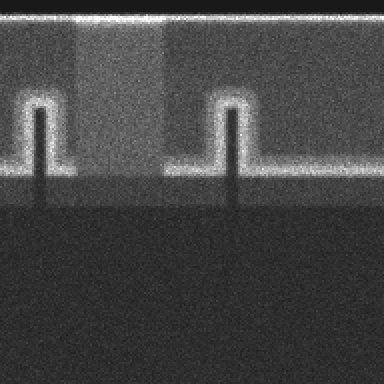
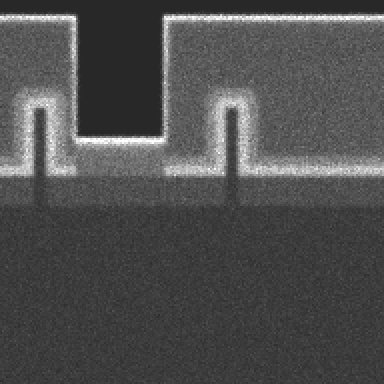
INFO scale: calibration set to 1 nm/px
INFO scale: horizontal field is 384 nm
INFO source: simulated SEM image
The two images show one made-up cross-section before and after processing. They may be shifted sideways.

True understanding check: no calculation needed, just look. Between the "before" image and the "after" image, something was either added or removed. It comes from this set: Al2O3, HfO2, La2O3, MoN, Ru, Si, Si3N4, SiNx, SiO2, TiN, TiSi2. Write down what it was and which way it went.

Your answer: SiO2 (removed)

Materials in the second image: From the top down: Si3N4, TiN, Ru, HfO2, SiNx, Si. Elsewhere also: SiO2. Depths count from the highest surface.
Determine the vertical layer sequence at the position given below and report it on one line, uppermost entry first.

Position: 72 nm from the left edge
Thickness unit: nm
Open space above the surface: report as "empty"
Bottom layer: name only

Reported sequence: Si3N4 44, TiN 96, Ru 10, HfO2 10, SiNx 30, Si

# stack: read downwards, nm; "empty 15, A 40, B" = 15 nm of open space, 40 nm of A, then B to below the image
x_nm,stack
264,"Si3N4 44, TiN 96, Ru 10, HfO2 10, SiNx 30, Si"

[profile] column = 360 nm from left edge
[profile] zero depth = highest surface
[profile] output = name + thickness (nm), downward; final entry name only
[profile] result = Si3N4 44, TiN 96, Ru 10, HfO2 10, SiNx 30, Si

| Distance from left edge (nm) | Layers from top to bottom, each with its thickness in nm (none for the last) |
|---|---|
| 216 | Si3N4 44, TiN 28, Ru 14, HfO2 74, SiNx 30, Si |